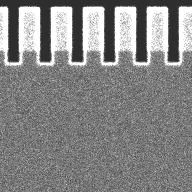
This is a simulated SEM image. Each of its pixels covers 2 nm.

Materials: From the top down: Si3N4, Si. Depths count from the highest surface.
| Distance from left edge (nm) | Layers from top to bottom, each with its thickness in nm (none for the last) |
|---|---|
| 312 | Si3N4 86, Si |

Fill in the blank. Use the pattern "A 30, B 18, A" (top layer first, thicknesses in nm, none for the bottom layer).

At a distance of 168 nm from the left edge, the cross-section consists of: Si3N4 86, Si